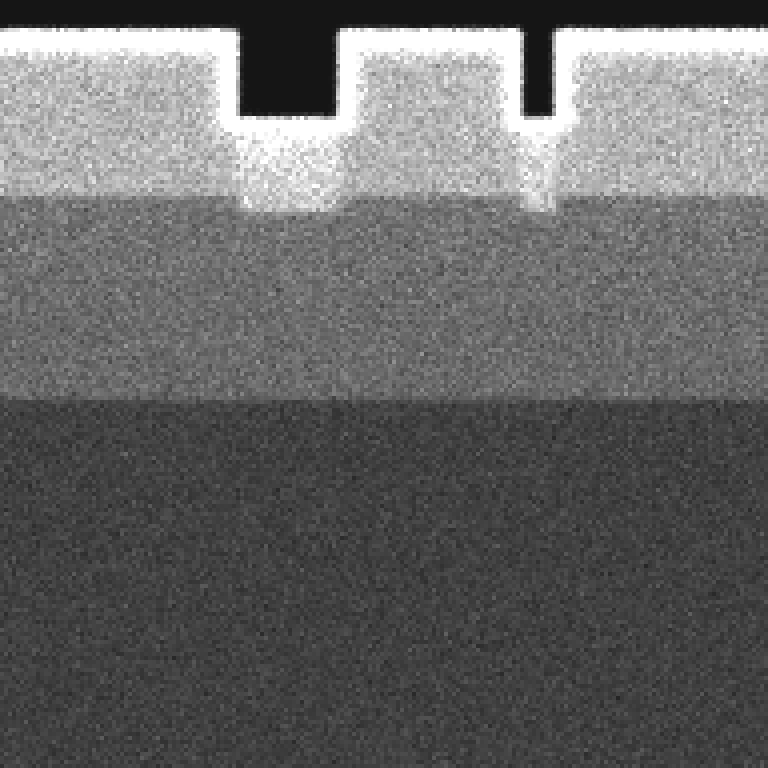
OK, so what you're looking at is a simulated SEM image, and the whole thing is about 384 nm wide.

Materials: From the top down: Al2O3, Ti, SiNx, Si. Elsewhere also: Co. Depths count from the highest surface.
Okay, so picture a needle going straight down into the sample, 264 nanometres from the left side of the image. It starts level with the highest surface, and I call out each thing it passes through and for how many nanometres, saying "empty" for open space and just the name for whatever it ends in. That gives empty 44, Co 46, Ti 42, SiNx 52, Si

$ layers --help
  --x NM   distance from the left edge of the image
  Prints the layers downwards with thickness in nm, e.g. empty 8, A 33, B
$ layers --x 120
empty 44, Co 46, Ti 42, SiNx 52, Si